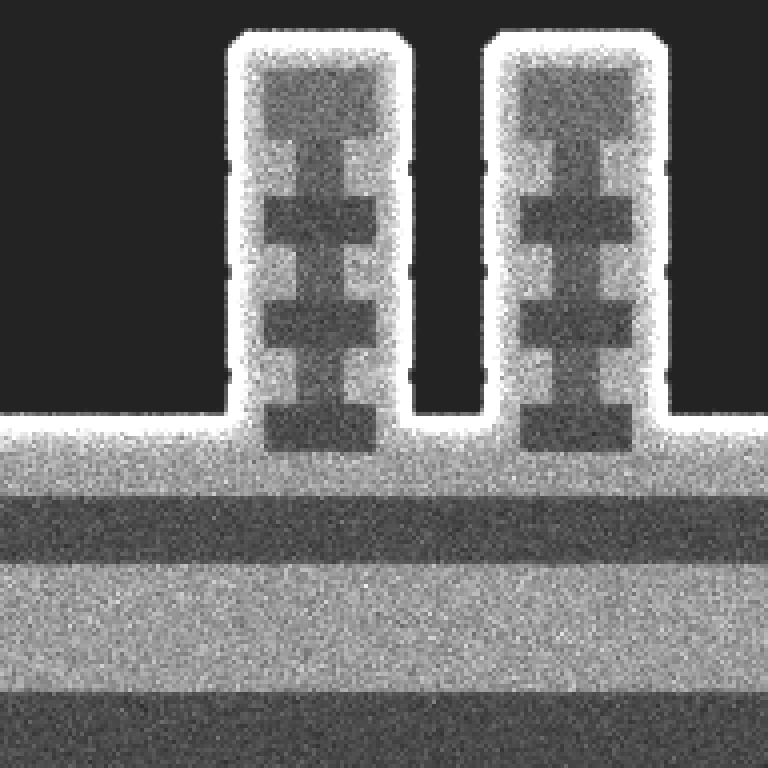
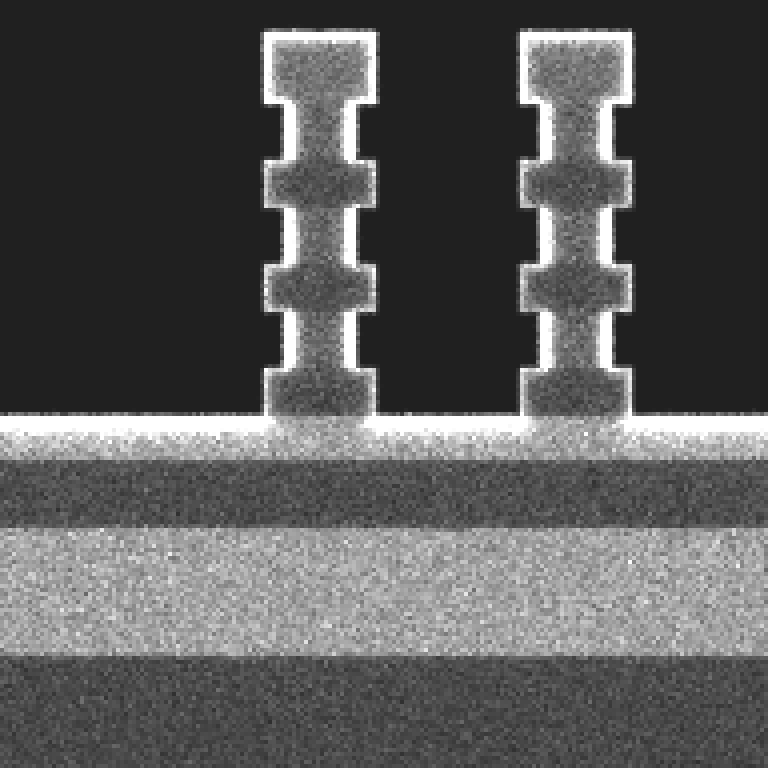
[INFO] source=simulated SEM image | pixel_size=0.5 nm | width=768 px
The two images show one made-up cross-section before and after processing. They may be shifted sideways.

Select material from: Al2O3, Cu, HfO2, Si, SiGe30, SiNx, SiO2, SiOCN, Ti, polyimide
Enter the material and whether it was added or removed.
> Al2O3 / removed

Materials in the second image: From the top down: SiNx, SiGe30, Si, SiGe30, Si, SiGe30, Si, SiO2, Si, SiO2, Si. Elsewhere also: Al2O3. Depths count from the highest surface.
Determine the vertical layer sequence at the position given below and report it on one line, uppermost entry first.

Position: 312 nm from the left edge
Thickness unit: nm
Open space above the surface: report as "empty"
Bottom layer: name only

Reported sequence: SiNx 36, empty 28, Si 24, empty 28, Si 24, empty 28, Si 24, SiO2 22, Si 34, SiO2 64, Si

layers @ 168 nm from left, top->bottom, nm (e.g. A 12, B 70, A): SiNx 36, SiGe30 28, Si 24, SiGe30 28, Si 24, SiGe30 28, Si 24, SiO2 22, Si 34, SiO2 64, Si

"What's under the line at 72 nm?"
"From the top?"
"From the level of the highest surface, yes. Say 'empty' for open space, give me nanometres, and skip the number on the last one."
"empty 192, SiO2 22, Si 34, SiO2 64, Si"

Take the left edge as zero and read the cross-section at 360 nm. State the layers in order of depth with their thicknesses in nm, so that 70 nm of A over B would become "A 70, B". empty 192, SiO2 22, Si 34, SiO2 64, Si